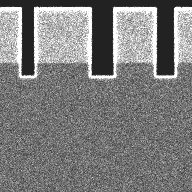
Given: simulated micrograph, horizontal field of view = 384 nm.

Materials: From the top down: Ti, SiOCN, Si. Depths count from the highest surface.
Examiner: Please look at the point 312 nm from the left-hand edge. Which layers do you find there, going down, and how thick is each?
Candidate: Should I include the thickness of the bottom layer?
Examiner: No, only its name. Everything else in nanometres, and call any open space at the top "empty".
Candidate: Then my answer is empty 136, Si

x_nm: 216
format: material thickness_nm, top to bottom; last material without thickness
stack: empty 136, Si